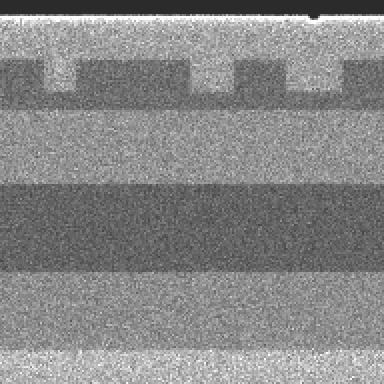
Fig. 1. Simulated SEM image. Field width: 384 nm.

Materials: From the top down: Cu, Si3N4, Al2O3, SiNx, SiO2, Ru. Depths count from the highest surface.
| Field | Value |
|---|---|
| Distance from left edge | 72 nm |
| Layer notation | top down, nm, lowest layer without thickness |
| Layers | Cu 76, Si3N4 18, Al2O3 74, SiNx 88, SiO2 78, Ru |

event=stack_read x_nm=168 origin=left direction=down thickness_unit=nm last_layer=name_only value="Cu 44, Si3N4 50, Al2O3 74, SiNx 88, SiO2 78, Ru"